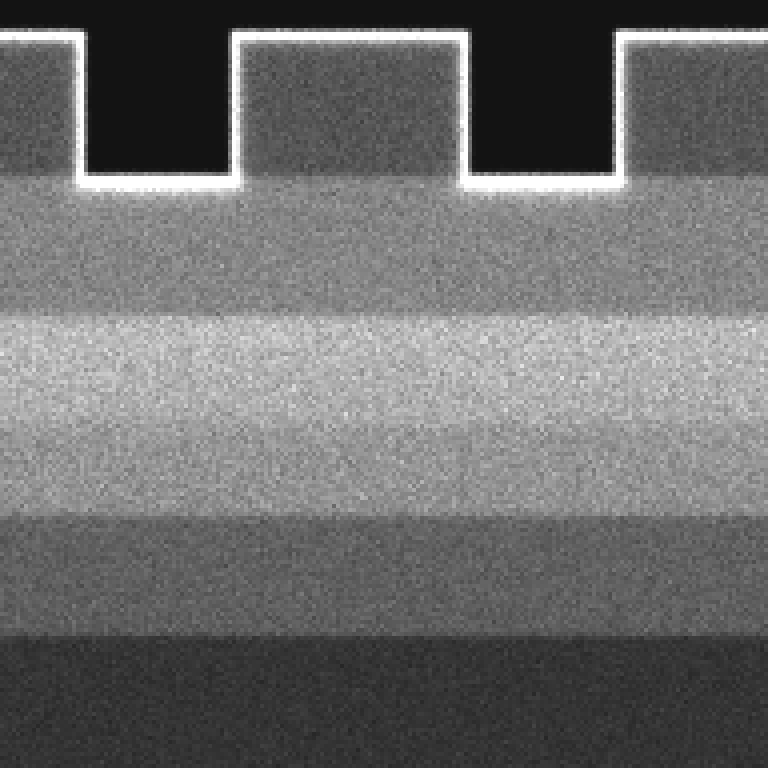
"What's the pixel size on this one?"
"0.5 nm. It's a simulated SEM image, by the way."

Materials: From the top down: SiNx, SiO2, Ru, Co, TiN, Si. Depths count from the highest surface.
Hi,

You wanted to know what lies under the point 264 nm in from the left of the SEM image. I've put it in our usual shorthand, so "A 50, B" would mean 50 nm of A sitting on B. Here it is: empty 72, SiO2 70, Ru 54, Co 46, TiN 60, Si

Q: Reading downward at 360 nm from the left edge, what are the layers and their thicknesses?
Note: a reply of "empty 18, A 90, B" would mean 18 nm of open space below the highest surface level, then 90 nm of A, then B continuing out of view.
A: SiNx 72, SiO2 70, Ru 54, Co 46, TiN 60, Si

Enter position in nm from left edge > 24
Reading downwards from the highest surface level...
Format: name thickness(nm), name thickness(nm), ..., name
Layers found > SiNx 72, SiO2 70, Ru 54, Co 46, TiN 60, Si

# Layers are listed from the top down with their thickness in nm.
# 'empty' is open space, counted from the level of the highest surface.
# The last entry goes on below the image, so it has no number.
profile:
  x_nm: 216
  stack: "SiNx 72, SiO2 70, Ru 54, Co 46, TiN 60, Si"